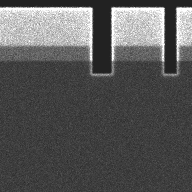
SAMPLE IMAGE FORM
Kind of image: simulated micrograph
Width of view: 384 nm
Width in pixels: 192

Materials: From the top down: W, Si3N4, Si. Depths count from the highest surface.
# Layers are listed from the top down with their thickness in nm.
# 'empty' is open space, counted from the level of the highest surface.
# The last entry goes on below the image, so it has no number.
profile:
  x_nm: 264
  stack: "W 76, Si3N4 30, Si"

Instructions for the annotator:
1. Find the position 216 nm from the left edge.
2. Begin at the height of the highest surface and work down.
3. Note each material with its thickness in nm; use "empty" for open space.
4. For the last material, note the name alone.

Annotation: empty 132, Si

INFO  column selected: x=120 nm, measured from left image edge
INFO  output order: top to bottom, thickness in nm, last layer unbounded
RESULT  W 76, Si3N4 30, Si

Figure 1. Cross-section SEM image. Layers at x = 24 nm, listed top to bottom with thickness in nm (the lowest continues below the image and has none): W 76, Si3N4 30, Si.